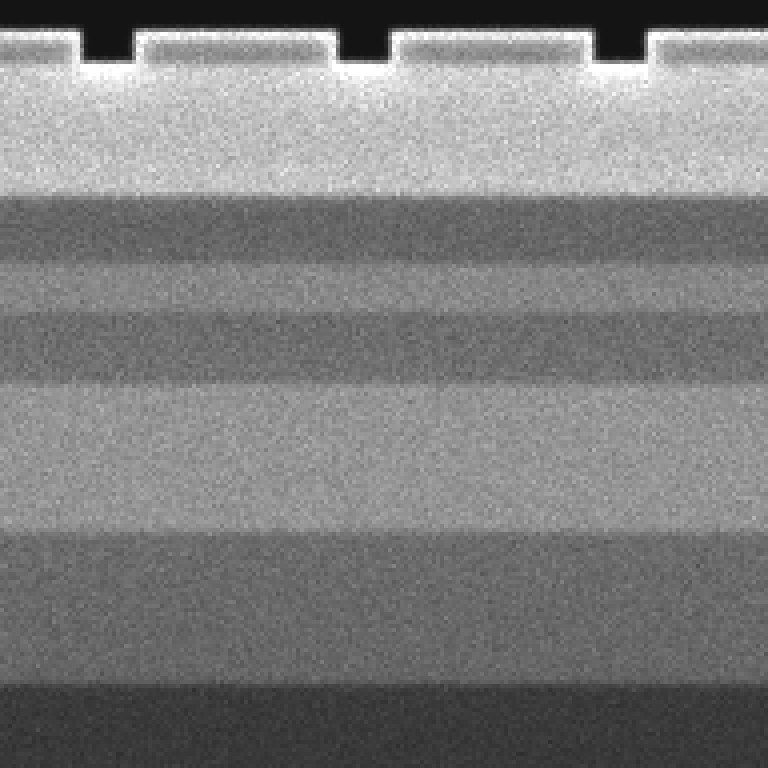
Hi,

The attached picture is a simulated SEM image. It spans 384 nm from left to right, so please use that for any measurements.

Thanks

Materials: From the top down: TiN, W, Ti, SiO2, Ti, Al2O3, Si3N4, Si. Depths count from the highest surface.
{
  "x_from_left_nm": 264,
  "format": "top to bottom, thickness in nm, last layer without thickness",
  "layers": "TiN 16, W 66, Ti 34, SiO2 24, Ti 36, Al2O3 74, Si3N4 76, Si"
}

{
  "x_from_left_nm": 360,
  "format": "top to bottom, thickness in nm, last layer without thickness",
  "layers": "TiN 16, W 66, Ti 34, SiO2 24, Ti 36, Al2O3 74, Si3N4 76, Si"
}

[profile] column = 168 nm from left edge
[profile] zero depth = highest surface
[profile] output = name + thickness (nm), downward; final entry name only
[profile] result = empty 16, W 66, Ti 34, SiO2 24, Ti 36, Al2O3 74, Si3N4 76, Si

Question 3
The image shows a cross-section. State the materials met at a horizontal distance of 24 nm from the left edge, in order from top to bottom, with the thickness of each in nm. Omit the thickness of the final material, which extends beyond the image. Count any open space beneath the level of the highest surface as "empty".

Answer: TiN 16, W 66, Ti 34, SiO2 24, Ti 36, Al2O3 74, Si3N4 76, Si